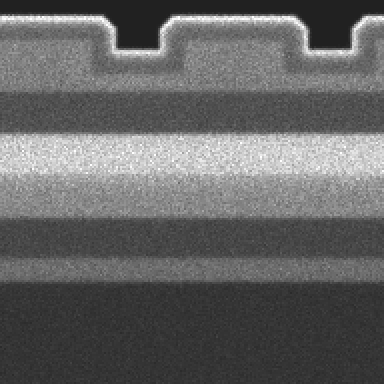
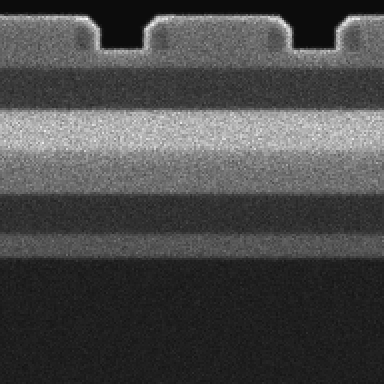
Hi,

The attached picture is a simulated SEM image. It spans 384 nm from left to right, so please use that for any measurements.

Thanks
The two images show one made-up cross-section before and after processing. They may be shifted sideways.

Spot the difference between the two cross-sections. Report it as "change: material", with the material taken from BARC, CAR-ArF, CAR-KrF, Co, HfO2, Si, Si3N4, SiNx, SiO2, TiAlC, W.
removed: SiO2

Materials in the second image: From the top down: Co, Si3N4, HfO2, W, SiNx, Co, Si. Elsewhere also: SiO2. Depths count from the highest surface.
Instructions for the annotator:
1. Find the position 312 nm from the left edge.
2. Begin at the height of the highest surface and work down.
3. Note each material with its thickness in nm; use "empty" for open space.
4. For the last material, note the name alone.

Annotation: empty 34, Co 18, Si3N4 42, HfO2 40, W 44, SiNx 40, Co 24, Si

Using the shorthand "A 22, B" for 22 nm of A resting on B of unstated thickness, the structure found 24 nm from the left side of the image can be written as Co 52, Si3N4 42, HfO2 40, W 44, SiNx 40, Co 24, Si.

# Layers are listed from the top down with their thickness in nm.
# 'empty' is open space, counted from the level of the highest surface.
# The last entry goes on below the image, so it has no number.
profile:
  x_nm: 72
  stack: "Co 52, Si3N4 42, HfO2 40, W 44, SiNx 40, Co 24, Si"